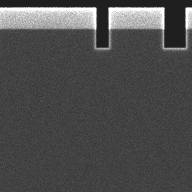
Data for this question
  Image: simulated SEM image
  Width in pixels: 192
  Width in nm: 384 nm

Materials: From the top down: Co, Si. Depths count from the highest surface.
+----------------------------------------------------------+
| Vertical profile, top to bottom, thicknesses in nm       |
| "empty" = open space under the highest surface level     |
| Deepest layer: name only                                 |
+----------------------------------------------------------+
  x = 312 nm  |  Co 42, Si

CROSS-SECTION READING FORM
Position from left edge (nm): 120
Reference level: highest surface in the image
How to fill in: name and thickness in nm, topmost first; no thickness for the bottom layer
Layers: Co 42, Si